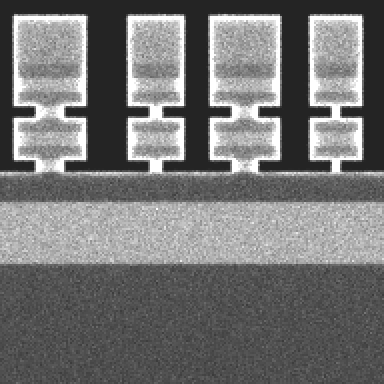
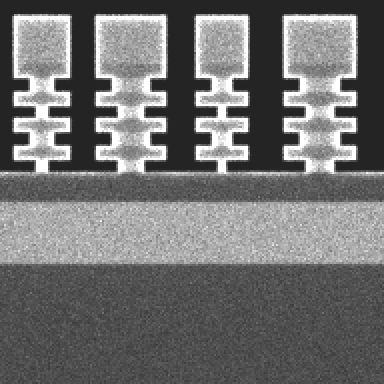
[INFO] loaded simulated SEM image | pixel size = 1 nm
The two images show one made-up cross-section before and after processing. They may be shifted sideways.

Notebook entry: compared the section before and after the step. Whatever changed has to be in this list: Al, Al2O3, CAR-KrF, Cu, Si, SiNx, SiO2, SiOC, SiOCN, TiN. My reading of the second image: SiO2 removed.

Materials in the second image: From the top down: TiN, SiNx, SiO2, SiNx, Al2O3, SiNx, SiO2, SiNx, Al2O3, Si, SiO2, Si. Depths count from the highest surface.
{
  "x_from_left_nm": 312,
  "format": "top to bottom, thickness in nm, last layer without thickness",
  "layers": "TiN 48, SiNx 14, SiO2 14, SiNx 14, Al2O3 12, SiNx 14, SiO2 14, SiNx 14, Al2O3 12, Si 30, SiO2 62, Si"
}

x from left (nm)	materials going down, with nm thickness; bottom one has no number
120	TiN 48, SiNx 14, SiO2 14, SiNx 14, Al2O3 12, SiNx 14, SiO2 14, SiNx 14, Al2O3 12, Si 30, SiO2 62, Si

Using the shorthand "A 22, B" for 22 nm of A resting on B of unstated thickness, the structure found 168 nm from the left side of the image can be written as empty 156, Si 30, SiO2 62, Si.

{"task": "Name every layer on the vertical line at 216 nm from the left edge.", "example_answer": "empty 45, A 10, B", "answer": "TiN 48, SiNx 14, SiO2 14, SiNx 14, empty 12, SiNx 14, SiO2 14, SiNx 14, empty 12, Si 30, SiO2 62, Si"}